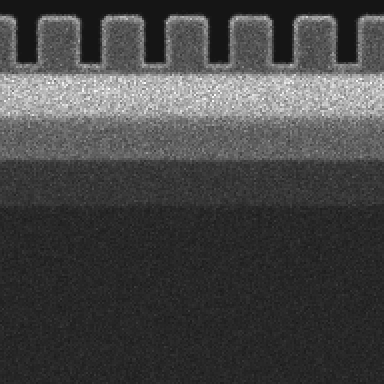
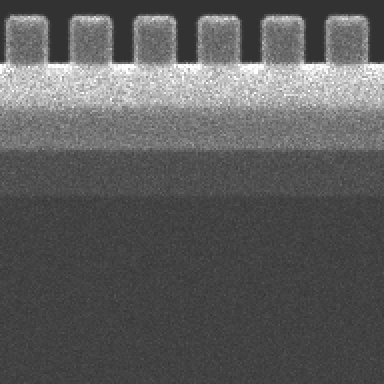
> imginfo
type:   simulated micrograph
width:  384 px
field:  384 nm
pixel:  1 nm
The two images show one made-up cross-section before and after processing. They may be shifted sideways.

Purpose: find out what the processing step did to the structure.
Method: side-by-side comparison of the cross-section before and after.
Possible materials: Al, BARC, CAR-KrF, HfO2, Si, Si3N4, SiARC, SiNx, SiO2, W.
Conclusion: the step removed Si3N4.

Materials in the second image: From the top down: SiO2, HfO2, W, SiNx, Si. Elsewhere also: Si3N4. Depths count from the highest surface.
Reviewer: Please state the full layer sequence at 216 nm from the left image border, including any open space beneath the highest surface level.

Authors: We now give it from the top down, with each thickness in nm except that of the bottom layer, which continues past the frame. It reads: SiO2 48, HfO2 42, W 44, SiNx 46, Si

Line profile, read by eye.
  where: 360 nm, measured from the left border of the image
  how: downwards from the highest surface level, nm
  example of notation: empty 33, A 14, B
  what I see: Si3N4 48, HfO2 42, W 44, SiNx 46, Si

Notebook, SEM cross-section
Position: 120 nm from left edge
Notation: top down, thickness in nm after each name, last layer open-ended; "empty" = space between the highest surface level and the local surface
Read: empty 48, HfO2 42, W 44, SiNx 46, Si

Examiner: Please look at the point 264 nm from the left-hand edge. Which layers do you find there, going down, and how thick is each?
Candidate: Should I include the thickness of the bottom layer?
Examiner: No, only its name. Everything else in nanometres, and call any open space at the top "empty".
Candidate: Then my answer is empty 2, Si3N4 46, HfO2 42, W 44, SiNx 46, Si